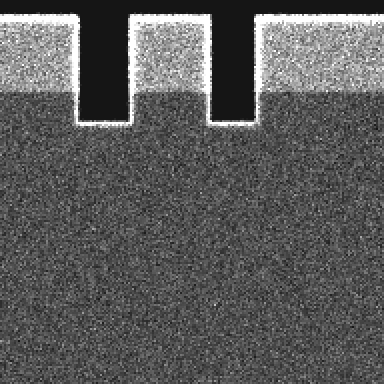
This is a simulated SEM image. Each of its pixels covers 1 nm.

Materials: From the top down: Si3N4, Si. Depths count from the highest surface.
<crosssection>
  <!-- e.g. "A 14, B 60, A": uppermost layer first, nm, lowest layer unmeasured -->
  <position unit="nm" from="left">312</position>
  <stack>Si3N4 76, Si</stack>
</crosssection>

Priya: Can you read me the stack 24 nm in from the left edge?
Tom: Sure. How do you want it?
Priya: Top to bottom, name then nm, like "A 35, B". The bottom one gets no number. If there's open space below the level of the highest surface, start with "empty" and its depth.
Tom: Si3N4 76, Si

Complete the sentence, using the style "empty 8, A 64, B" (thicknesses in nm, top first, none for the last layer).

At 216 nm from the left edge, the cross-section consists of empty 106, Si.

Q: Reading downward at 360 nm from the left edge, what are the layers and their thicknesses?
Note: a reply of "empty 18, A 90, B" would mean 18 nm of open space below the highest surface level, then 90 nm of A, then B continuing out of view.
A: Si3N4 76, Si